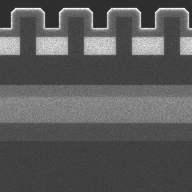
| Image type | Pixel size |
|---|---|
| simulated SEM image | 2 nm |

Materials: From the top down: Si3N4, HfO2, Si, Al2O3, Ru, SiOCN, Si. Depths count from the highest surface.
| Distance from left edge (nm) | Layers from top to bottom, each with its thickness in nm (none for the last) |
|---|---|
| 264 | Si3N4 58, HfO2 36, Si 60, Al2O3 24, Ru 52, SiOCN 36, Si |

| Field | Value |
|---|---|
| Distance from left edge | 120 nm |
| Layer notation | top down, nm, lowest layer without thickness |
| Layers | empty 6, Si3N4 52, HfO2 36, Si 60, Al2O3 24, Ru 52, SiOCN 36, Si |